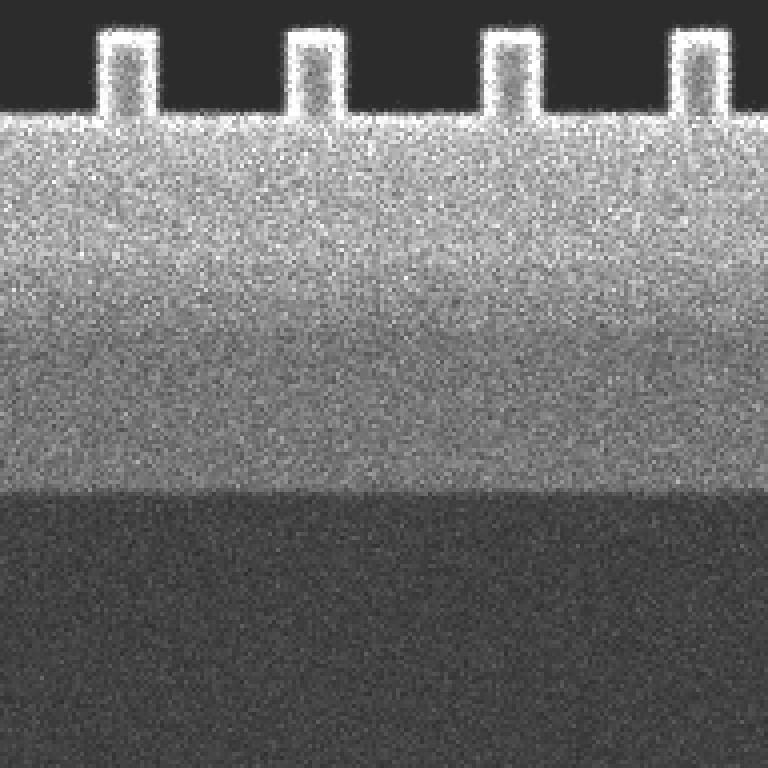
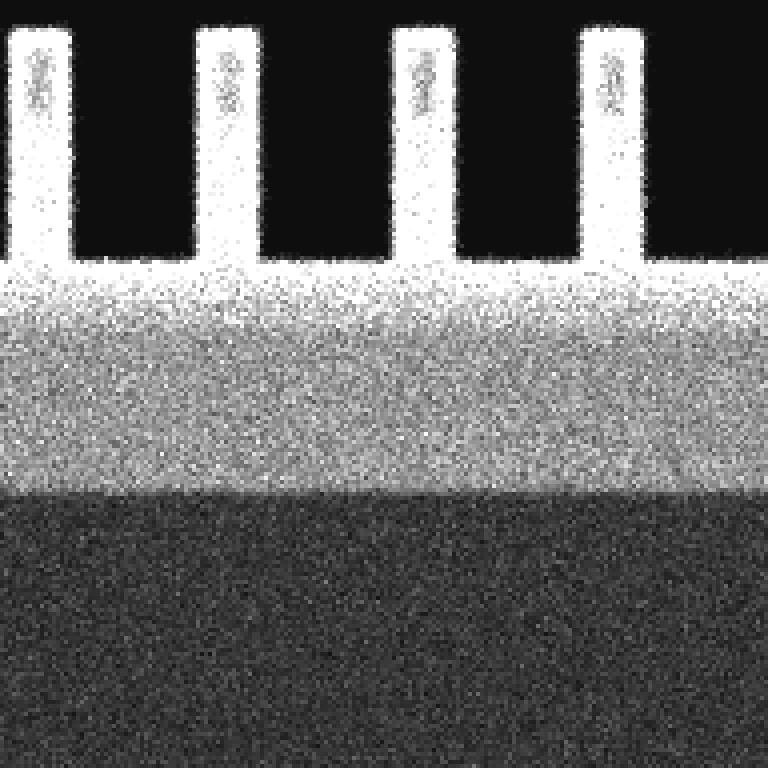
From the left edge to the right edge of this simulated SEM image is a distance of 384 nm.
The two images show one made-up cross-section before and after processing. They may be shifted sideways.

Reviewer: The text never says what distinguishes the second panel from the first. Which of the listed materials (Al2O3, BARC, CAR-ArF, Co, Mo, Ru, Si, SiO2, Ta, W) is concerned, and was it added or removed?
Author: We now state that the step removed W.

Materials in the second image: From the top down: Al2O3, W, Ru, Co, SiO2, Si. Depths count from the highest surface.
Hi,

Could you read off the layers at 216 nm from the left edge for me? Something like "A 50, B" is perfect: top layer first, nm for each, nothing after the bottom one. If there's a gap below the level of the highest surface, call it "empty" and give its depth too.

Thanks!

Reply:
Al2O3 42, W 74, Ru 16, Co 16, SiO2 82, Si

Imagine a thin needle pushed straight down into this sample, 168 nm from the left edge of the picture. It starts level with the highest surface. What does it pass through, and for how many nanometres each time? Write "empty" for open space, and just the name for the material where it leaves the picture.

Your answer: empty 116, Ru 16, Co 16, SiO2 82, Si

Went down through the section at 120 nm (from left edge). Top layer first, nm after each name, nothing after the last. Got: Al2O3 42, W 74, Ru 16, Co 16, SiO2 82, Si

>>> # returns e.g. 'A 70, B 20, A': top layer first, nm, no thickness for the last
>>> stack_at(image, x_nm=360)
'empty 116, Ru 16, Co 16, SiO2 82, Si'